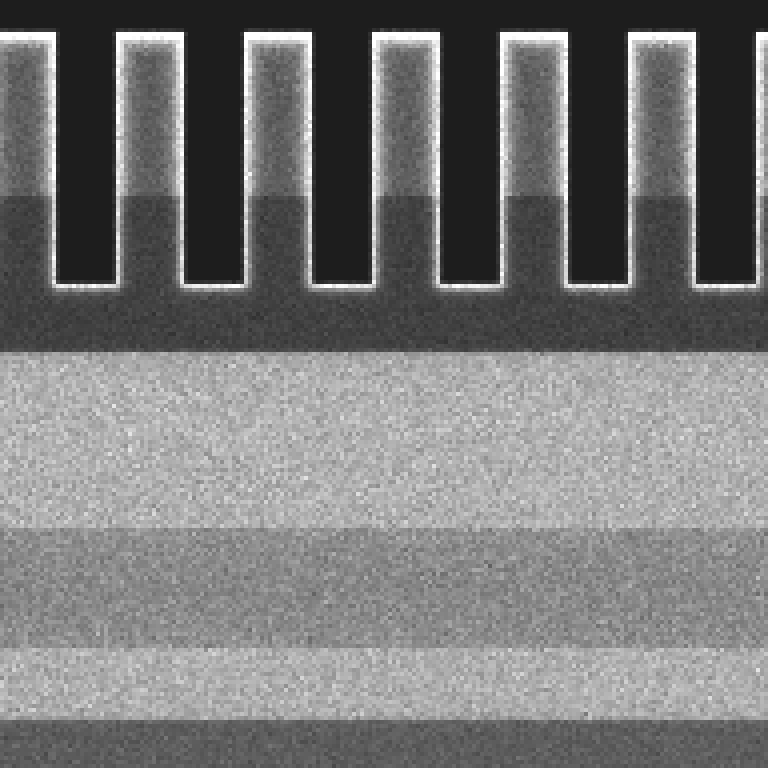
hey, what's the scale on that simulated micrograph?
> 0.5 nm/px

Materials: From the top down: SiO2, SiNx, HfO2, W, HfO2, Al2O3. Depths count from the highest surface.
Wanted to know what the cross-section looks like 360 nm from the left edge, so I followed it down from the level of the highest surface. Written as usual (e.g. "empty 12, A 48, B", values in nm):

empty 126, SiNx 34, HfO2 88, W 60, HfO2 36, Al2O3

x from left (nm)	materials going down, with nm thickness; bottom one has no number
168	empty 126, SiNx 34, HfO2 88, W 60, HfO2 36, Al2O3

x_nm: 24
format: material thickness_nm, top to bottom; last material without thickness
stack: SiO2 82, SiNx 78, HfO2 88, W 60, HfO2 36, Al2O3